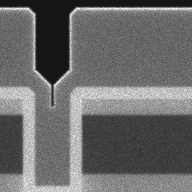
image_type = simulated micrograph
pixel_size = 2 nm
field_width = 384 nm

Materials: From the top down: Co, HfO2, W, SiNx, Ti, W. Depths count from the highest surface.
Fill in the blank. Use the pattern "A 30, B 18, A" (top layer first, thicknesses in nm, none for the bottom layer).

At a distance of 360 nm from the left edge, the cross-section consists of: Co 158, HfO2 24, W 32, SiNx 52, Ti 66, W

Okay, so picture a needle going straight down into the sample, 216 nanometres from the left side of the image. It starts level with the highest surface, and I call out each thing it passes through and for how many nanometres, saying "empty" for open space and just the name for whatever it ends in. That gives Co 158, HfO2 24, W 32, SiNx 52, Ti 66, W